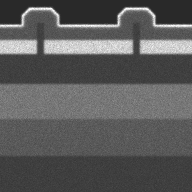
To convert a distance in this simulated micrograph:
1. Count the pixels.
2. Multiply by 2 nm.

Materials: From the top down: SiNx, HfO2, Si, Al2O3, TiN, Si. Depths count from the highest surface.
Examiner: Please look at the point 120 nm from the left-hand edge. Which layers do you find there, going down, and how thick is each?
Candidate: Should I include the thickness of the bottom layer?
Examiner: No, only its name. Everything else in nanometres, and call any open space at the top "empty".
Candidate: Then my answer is empty 34, SiNx 30, HfO2 28, Si 60, Al2O3 70, TiN 74, Si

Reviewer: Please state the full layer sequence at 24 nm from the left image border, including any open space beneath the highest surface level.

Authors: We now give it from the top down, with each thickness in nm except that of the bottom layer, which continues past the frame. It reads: empty 34, SiNx 30, HfO2 28, Si 60, Al2O3 70, TiN 74, Si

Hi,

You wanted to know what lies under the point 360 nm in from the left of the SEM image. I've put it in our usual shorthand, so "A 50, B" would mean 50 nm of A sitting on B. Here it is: empty 34, SiNx 30, HfO2 28, Si 60, Al2O3 70, TiN 74, Si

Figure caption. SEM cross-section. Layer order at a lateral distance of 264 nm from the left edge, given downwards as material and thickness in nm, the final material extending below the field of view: SiNx 64, HfO2 28, Si 60, Al2O3 70, TiN 74, Si